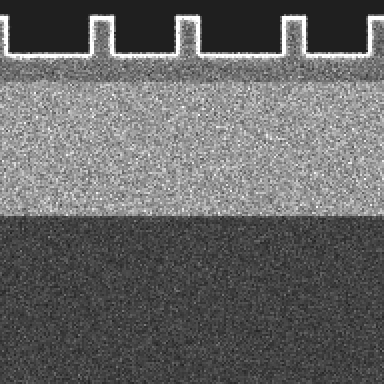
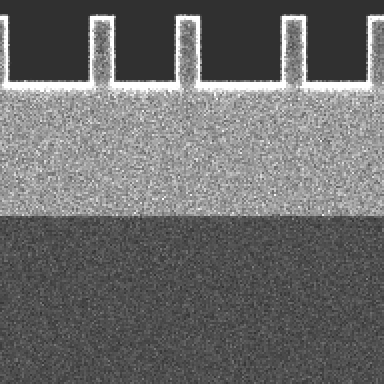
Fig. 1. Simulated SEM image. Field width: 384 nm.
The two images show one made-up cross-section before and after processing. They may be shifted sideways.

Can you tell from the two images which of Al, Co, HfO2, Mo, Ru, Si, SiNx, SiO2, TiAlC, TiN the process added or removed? Yes, it removed TiN.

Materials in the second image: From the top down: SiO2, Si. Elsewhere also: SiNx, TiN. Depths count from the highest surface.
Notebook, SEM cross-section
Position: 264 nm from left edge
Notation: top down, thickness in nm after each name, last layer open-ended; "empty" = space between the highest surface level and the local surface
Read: empty 66, SiO2 134, Si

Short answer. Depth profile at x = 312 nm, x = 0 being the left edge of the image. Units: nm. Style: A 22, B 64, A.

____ empty 66, SiO2 134, Si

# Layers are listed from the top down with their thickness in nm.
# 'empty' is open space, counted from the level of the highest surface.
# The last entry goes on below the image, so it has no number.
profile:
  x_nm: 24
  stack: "empty 66, SiO2 134, Si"